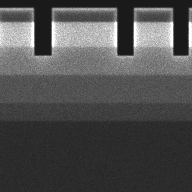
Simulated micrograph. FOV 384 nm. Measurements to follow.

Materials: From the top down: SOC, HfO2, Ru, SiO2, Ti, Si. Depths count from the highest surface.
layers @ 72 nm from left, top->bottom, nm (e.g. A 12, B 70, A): empty 96, Ru 38, SiO2 56, Ti 36, Si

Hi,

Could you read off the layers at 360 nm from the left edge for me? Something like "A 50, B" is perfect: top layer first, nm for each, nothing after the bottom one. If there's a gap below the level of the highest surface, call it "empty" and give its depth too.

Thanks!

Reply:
empty 96, Ru 38, SiO2 56, Ti 36, Si